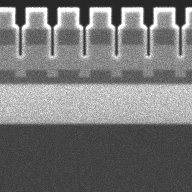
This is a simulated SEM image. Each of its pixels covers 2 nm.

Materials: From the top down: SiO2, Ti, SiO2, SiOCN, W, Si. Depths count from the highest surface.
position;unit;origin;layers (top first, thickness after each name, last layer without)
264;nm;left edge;SiO2 42, Ti 32, SiO2 50, SiOCN 28, W 80, Si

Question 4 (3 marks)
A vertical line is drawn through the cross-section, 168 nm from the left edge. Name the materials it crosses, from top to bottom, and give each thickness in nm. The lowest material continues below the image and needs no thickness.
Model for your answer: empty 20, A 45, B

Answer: empty 96, SiO2 42, SiOCN 14, W 80, Si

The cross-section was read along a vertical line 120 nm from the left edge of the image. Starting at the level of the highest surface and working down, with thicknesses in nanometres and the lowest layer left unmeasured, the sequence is SiO2 42, Ti 32, SiO2 50, SiOCN 28, W 80, Si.